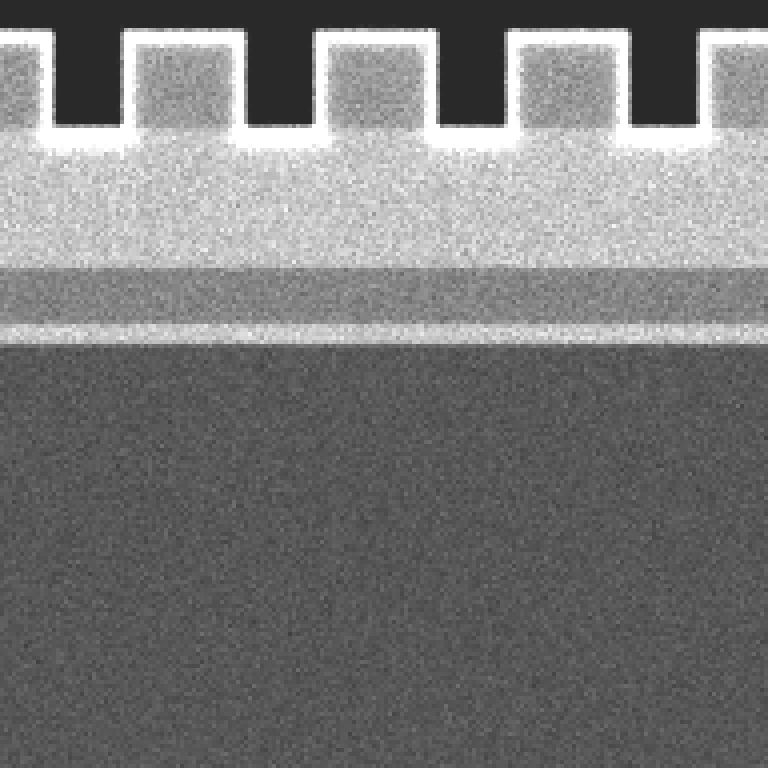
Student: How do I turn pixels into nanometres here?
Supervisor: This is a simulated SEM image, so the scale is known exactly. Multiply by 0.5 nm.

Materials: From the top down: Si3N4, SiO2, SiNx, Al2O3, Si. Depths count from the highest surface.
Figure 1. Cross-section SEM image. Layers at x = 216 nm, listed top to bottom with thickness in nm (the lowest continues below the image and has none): Si3N4 48, SiO2 70, SiNx 28, Al2O3 10, Si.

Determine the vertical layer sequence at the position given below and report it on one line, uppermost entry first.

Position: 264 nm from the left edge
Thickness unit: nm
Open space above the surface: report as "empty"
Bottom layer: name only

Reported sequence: Si3N4 48, SiO2 70, SiNx 28, Al2O3 10, Si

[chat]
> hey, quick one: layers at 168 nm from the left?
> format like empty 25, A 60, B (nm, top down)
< Si3N4 48, SiO2 70, SiNx 28, Al2O3 10, Si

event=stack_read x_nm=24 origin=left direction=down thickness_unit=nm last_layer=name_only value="Si3N4 48, SiO2 70, SiNx 28, Al2O3 10, Si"